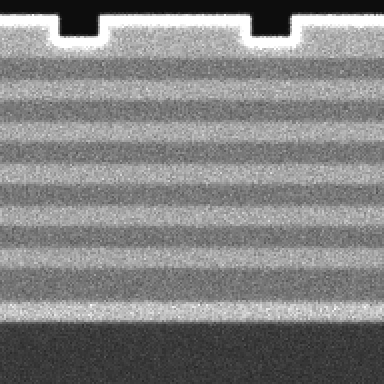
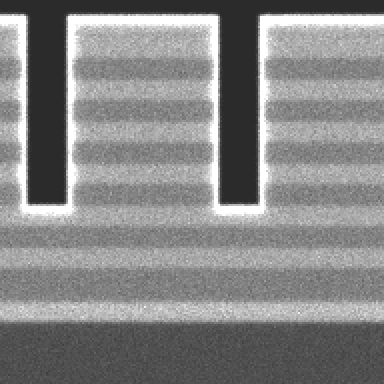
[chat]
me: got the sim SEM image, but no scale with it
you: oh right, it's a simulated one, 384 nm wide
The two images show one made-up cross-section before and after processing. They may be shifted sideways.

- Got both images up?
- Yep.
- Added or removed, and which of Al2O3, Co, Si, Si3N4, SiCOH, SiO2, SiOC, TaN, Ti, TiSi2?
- removed, Al2O3 and Si3N4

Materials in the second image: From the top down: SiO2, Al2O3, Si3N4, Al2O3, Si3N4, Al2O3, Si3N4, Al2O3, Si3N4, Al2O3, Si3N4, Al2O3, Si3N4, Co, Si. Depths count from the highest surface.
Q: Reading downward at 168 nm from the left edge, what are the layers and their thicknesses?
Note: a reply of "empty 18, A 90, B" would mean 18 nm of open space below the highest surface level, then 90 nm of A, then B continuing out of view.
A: SiO2 22, Al2O3 20, Si3N4 22, Al2O3 20, Si3N4 22, Al2O3 20, Si3N4 22, Al2O3 20, Si3N4 22, Al2O3 20, Si3N4 22, Al2O3 20, Si3N4 34, Co 20, Si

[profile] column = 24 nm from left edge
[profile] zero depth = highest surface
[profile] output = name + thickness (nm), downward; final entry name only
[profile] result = SiO2 22, Al2O3 20, Si3N4 22, Al2O3 20, Si3N4 22, Al2O3 20, Si3N4 22, Al2O3 20, Si3N4 22, Al2O3 20, Si3N4 22, Al2O3 20, Si3N4 34, Co 20, Si